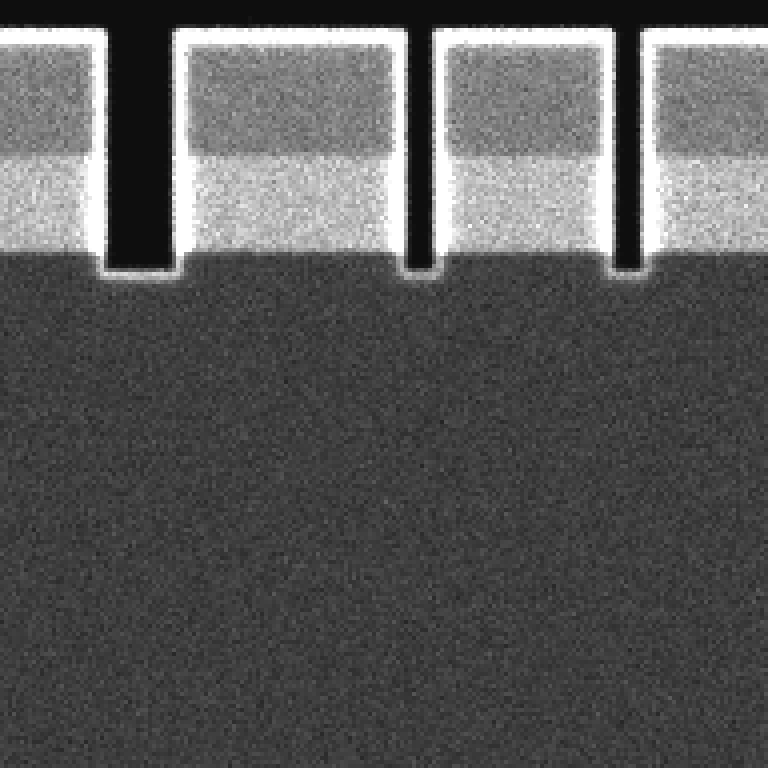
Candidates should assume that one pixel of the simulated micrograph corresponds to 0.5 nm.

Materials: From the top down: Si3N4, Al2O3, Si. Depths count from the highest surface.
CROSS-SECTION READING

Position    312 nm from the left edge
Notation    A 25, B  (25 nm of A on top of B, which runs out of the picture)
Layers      empty 120, Si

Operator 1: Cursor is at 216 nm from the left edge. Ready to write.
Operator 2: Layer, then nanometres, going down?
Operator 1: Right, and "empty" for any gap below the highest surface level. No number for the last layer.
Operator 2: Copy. empty 120, Si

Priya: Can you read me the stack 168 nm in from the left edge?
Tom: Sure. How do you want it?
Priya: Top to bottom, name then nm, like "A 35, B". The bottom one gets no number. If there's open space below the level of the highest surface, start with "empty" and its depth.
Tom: Si3N4 62, Al2O3 48, Si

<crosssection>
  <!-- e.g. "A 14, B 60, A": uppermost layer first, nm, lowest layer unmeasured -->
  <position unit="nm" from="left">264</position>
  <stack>Si3N4 62, Al2O3 48, Si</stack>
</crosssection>